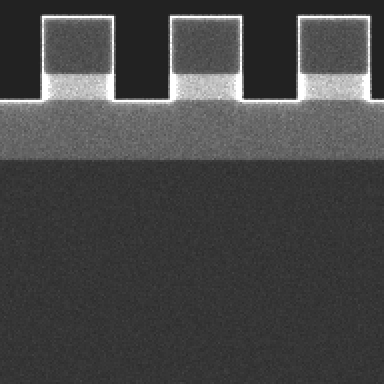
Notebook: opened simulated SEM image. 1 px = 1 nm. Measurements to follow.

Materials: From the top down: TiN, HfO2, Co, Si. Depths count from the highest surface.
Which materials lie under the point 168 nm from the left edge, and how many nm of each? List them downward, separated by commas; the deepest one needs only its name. empty 84, Co 60, Si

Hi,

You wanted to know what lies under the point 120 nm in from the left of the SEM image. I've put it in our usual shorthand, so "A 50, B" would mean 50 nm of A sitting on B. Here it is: empty 84, Co 60, Si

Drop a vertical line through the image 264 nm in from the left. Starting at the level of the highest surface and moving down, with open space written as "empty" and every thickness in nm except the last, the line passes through empty 84, Co 60, Si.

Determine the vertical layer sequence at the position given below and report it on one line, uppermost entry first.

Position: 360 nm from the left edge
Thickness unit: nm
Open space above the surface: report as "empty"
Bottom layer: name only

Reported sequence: TiN 58, HfO2 26, Co 60, Si